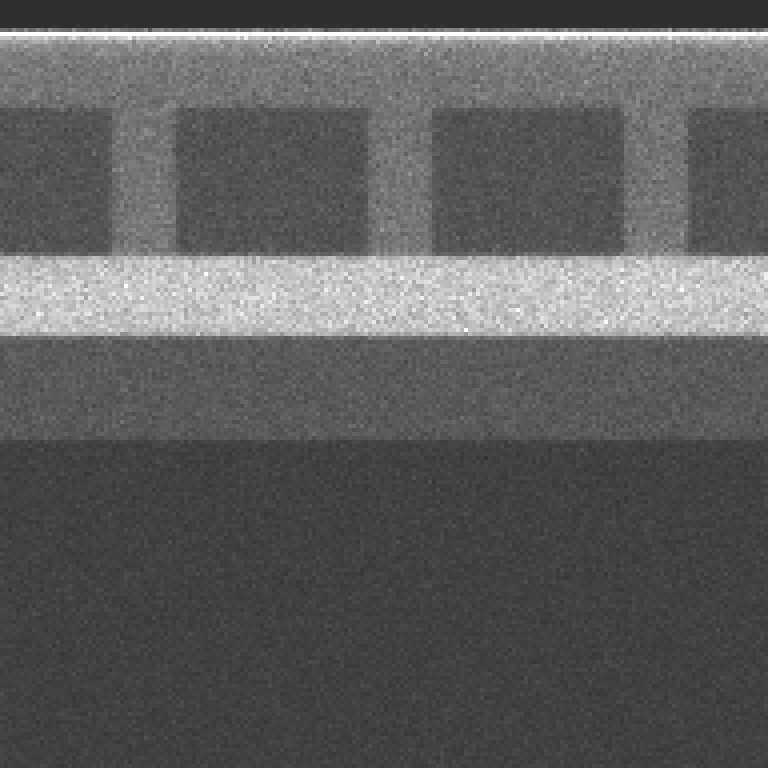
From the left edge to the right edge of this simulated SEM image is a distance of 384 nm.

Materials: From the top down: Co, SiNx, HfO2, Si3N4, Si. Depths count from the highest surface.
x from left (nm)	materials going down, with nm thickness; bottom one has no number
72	Co 112, HfO2 40, Si3N4 52, Si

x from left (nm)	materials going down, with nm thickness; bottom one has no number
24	Co 38, SiNx 74, HfO2 40, Si3N4 52, Si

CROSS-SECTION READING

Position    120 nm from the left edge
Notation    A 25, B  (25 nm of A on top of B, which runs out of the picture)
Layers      Co 38, SiNx 74, HfO2 40, Si3N4 52, Si